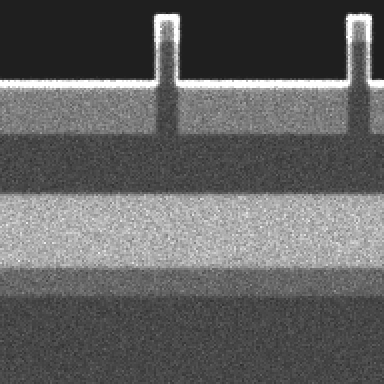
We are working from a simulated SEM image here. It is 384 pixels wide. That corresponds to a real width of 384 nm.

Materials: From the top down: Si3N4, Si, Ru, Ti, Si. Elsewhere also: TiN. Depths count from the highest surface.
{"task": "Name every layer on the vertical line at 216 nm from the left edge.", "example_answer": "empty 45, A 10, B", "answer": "empty 66, Si3N4 52, Si 60, Ru 74, Ti 28, Si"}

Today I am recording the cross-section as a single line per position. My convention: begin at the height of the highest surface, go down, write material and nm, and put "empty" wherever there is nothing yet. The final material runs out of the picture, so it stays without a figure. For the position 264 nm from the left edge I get empty 66, Si3N4 52, Si 60, Ru 74, Ti 28, Si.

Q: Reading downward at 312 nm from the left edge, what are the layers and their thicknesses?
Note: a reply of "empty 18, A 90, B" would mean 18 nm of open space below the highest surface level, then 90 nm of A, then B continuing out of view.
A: empty 66, Si3N4 52, Si 60, Ru 74, Ti 28, Si